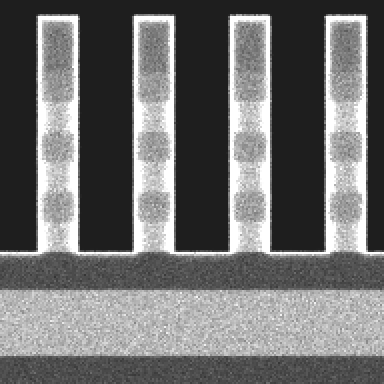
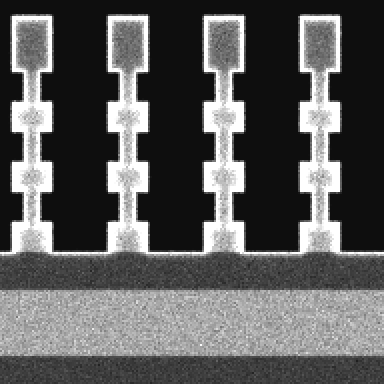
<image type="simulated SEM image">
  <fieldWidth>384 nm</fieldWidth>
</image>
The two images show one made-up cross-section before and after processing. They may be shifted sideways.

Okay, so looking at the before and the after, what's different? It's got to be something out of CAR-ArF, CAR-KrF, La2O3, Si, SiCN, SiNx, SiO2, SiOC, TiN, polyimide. TiN, removed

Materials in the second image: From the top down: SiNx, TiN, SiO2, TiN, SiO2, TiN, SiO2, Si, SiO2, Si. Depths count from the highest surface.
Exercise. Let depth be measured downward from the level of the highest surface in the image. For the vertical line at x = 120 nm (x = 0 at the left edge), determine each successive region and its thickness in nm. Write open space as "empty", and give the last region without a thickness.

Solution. SiNx 56, TiN 30, SiO2 30, TiN 30, SiO2 30, TiN 30, SiO2 30, Si 38, SiO2 66, Si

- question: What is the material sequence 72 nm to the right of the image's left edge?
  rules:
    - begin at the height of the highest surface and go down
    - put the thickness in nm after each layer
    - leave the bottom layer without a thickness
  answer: empty 236, Si 38, SiO2 66, Si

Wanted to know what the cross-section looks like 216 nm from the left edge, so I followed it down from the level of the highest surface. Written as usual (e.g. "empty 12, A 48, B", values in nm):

SiNx 56, TiN 30, SiO2 30, TiN 30, SiO2 30, TiN 30, SiO2 30, Si 38, SiO2 66, Si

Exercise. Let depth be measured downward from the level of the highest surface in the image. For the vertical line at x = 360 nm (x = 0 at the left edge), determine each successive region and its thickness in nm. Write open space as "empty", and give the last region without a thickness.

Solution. empty 236, Si 38, SiO2 66, Si